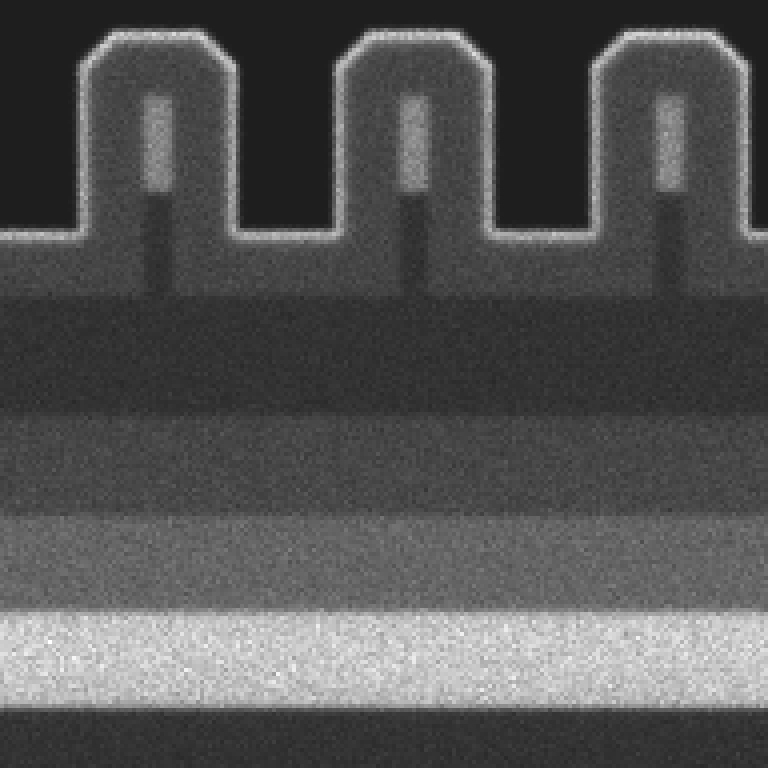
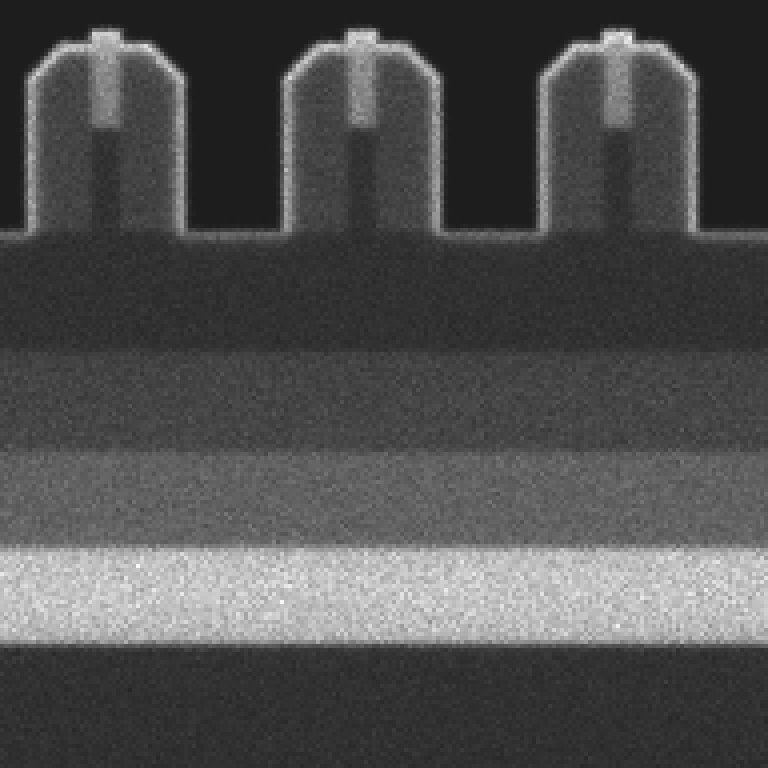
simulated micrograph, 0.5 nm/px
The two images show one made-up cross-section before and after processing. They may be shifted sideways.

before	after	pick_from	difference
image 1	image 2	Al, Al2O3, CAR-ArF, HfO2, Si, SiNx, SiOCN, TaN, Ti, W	SiNx removed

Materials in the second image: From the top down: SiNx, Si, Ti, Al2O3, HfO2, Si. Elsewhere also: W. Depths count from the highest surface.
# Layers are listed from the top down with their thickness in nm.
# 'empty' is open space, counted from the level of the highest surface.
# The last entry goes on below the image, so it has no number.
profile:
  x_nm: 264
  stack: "empty 100, Si 60, Ti 50, Al2O3 48, HfO2 48, Si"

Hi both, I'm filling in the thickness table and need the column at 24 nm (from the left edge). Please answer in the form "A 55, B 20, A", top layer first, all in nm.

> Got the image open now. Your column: empty 12, SiNx 88, Si 60, Ti 50, Al2O3 48, HfO2 48, Si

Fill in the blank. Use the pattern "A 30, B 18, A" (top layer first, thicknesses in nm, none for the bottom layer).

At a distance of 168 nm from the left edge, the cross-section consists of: empty 6, SiNx 94, Si 60, Ti 50, Al2O3 48, HfO2 48, Si